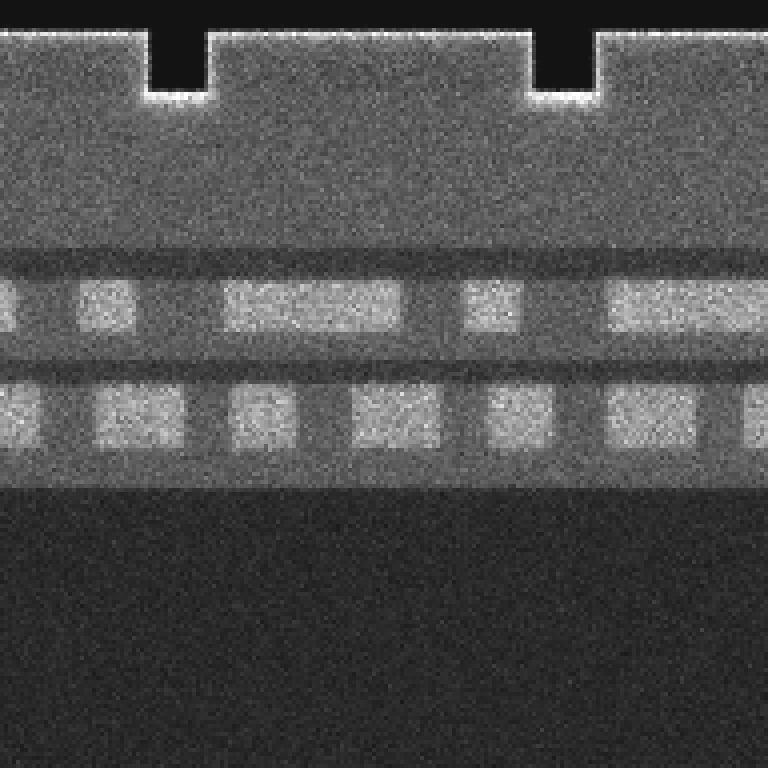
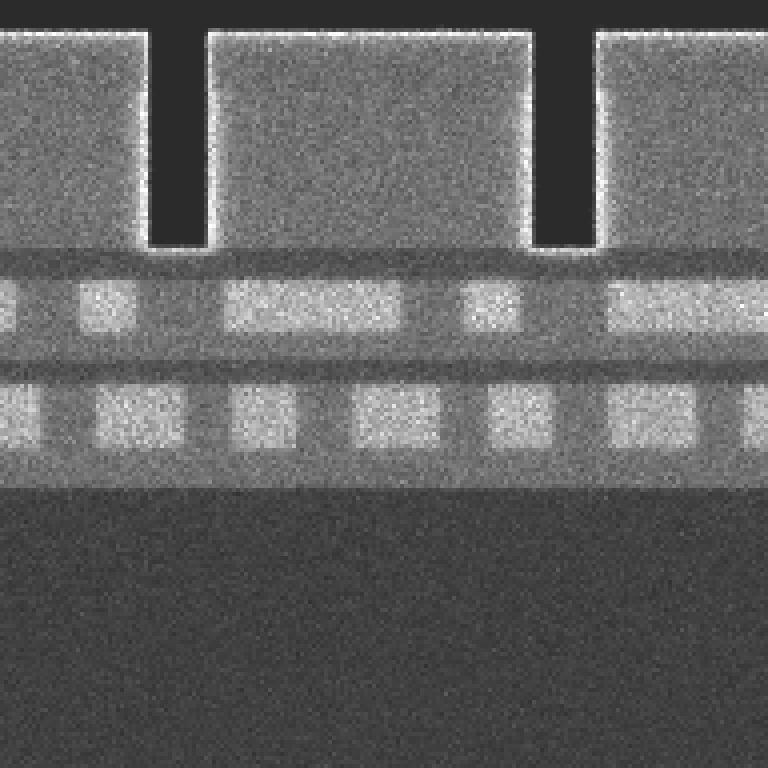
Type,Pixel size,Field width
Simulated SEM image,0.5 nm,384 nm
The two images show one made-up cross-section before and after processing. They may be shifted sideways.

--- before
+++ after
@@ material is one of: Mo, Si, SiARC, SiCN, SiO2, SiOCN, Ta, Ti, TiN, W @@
SiO2 removed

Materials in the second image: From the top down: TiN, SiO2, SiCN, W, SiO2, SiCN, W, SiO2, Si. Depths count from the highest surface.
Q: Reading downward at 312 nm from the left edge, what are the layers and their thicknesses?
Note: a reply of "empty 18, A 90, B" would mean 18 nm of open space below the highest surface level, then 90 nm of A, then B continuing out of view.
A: TiN 30, SiO2 78, SiCN 16, W 26, SiO2 14, SiCN 12, W 32, SiO2 20, Si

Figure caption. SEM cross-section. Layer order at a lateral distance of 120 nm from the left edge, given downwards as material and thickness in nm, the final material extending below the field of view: TiN 30, SiO2 78, SiCN 16, W 26, SiO2 14, SiCN 12, W 32, SiO2 20, Si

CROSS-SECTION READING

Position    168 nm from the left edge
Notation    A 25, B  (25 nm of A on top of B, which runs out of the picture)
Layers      TiN 30, SiO2 78, SiCN 16, W 26, SiO2 14, SiCN 12, SiO2 52, Si